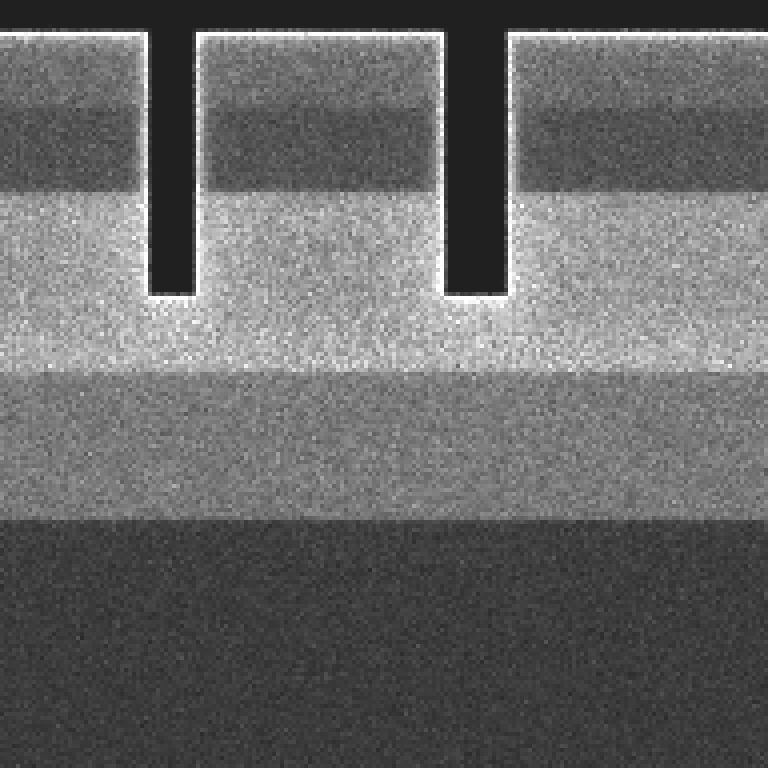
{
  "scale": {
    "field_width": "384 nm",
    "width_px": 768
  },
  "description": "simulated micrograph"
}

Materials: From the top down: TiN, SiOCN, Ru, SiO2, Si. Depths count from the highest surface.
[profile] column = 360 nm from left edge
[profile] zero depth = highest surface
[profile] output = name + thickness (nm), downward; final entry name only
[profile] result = TiN 38, SiOCN 42, Ru 90, SiO2 74, Si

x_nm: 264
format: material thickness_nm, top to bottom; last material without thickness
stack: TiN 38, SiOCN 42, Ru 90, SiO2 74, Si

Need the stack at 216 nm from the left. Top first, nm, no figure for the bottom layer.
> TiN 38, SiOCN 42, Ru 90, SiO2 74, Si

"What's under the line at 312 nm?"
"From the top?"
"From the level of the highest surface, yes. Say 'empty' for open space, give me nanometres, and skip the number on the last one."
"TiN 38, SiOCN 42, Ru 90, SiO2 74, Si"